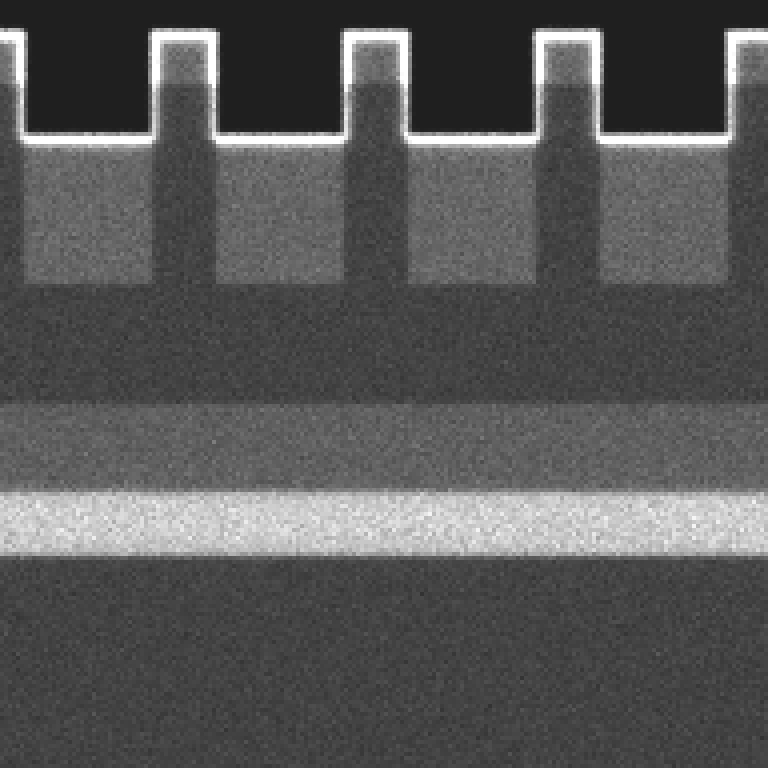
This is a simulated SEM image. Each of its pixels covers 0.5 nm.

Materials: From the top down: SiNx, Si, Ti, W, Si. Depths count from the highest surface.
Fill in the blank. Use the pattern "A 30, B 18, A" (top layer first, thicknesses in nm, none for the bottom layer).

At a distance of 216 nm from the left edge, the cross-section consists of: empty 52, SiNx 74, Si 60, Ti 44, W 32, Si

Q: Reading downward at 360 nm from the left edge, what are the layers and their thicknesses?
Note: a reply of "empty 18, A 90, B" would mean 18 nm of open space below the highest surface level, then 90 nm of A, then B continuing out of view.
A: empty 52, SiNx 74, Si 60, Ti 44, W 32, Si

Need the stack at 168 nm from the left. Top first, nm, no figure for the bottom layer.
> empty 52, SiNx 74, Si 60, Ti 44, W 32, Si